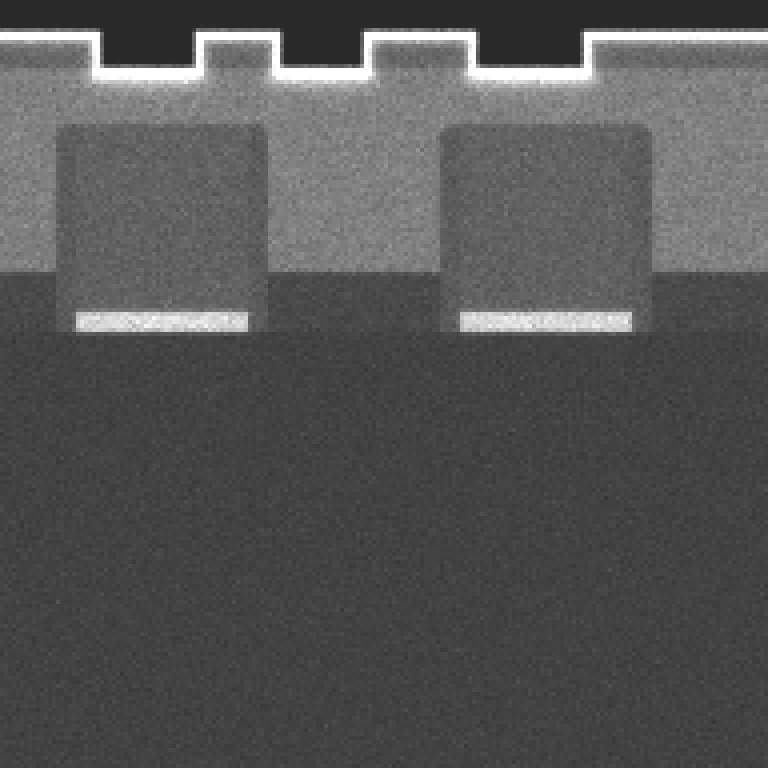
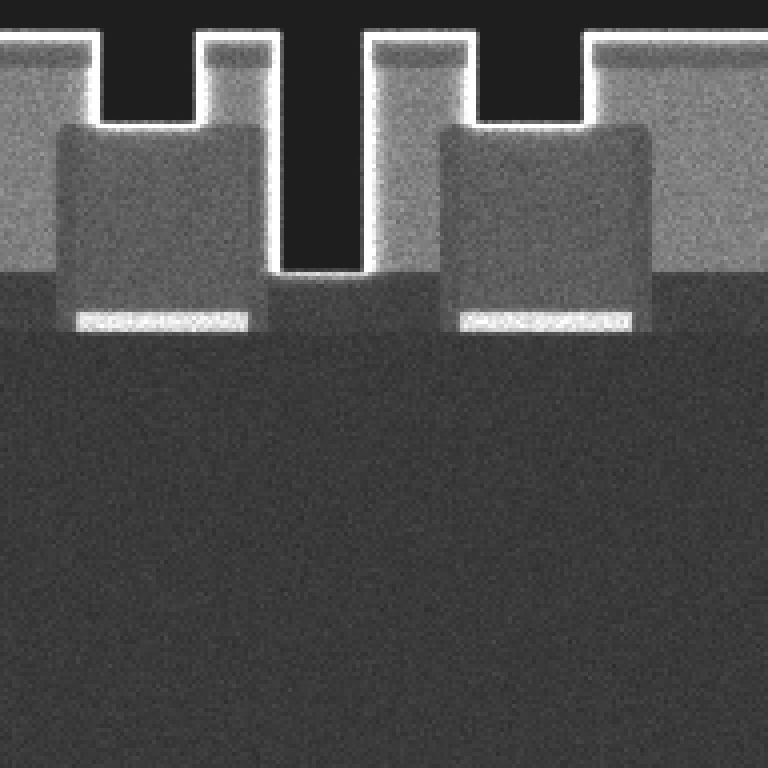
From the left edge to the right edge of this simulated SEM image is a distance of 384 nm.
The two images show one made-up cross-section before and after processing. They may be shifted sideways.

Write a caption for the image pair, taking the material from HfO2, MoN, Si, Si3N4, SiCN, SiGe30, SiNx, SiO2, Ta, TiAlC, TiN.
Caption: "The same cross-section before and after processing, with SiO2 removed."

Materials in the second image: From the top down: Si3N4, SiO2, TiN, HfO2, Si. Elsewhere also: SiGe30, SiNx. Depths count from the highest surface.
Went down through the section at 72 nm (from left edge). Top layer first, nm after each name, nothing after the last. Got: empty 46, TiN 94, HfO2 10, Si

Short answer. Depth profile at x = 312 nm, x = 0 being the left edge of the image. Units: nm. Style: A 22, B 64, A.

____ Si3N4 18, SiO2 28, TiN 94, HfO2 10, Si